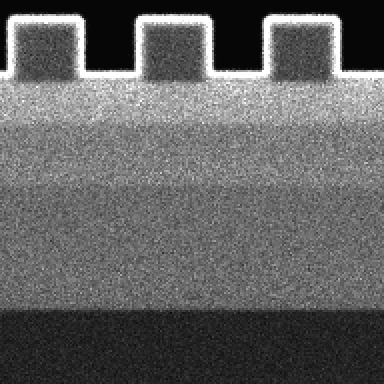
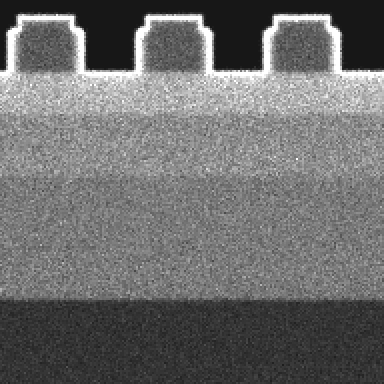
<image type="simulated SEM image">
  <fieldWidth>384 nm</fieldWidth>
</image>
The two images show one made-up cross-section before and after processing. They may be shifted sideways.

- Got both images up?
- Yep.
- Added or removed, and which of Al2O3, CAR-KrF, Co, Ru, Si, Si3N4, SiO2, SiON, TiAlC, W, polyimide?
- removed, Al2O3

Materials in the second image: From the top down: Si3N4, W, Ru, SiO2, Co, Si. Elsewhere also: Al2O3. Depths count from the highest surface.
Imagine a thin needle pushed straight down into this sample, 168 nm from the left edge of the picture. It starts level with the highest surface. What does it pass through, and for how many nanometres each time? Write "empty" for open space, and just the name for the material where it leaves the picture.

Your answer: Si3N4 56, W 42, Ru 62, SiO2 80, Co 44, Si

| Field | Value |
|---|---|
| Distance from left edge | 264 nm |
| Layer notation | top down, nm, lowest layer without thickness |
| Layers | empty 16, Al2O3 40, W 42, Ru 62, SiO2 80, Co 44, Si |